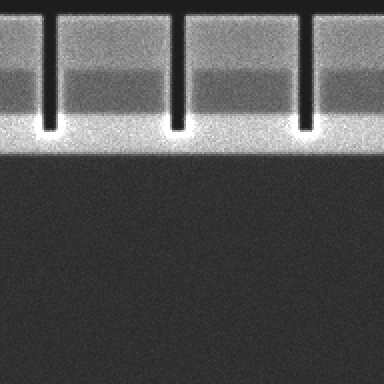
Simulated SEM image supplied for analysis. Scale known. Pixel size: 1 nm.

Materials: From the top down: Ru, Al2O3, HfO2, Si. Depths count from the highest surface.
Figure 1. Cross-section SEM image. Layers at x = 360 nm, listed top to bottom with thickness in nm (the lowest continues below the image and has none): Ru 54, Al2O3 44, HfO2 40, Si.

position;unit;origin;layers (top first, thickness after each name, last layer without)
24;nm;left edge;Ru 54, Al2O3 44, HfO2 40, Si